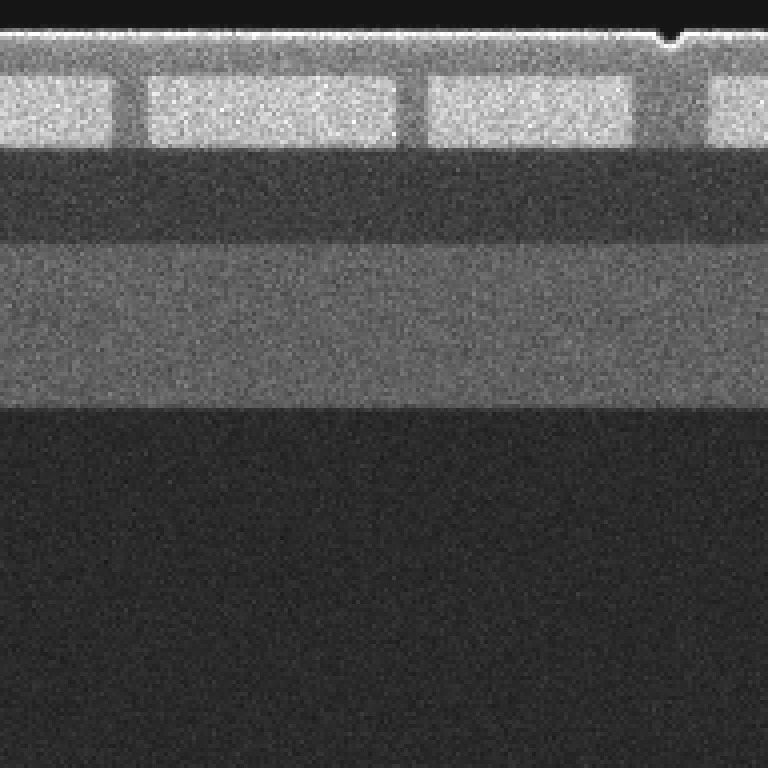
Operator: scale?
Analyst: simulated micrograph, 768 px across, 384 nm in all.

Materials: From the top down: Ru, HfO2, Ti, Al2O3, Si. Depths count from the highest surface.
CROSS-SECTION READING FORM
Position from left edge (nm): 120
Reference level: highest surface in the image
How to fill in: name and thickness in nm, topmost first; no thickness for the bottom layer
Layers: Ru 22, HfO2 36, Ti 48, Al2O3 82, Si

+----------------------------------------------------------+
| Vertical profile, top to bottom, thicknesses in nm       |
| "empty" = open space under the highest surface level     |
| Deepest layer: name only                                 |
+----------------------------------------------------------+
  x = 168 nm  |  Ru 22, HfO2 36, Ti 48, Al2O3 82, Si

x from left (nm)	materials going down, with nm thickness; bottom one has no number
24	Ru 22, HfO2 36, Ti 48, Al2O3 82, Si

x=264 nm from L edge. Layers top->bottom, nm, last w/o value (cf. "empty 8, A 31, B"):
Ru 22, HfO2 36, Ti 48, Al2O3 82, Si